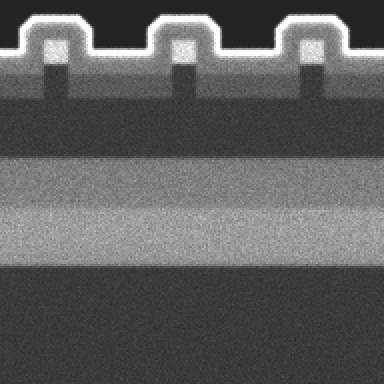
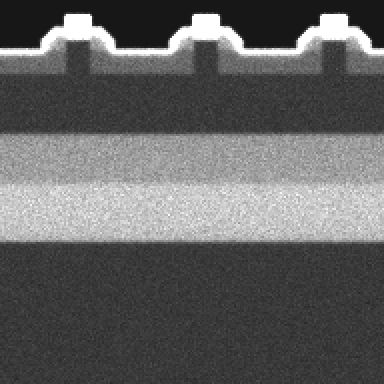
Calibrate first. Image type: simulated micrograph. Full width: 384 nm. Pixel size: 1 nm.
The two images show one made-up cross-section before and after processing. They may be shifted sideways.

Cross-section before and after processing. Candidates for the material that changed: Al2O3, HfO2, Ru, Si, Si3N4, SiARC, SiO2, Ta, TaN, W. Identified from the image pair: Al2O3 (removed).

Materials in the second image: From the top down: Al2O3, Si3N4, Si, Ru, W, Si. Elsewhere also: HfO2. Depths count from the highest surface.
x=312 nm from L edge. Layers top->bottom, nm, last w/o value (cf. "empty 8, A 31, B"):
empty 12, Al2O3 22, Si3N4 24, Si 60, Ru 50, W 58, Si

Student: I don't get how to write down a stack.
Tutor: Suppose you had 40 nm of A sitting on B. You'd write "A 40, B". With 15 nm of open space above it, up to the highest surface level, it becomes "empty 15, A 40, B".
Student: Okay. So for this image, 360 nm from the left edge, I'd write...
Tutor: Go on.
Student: empty 16, Al2O3 18, Si3N4 24, Si 60, Ru 50, W 58, Si